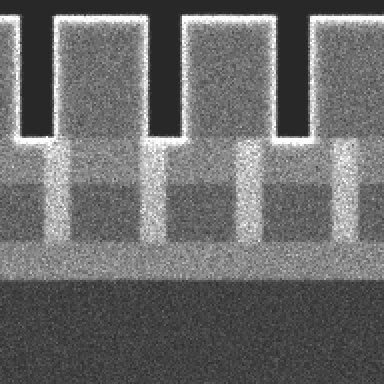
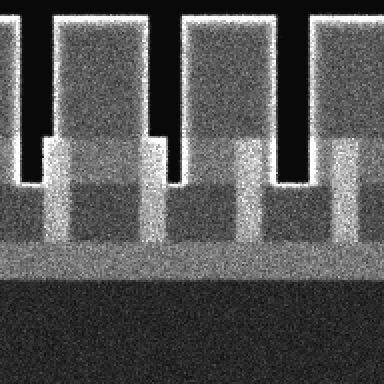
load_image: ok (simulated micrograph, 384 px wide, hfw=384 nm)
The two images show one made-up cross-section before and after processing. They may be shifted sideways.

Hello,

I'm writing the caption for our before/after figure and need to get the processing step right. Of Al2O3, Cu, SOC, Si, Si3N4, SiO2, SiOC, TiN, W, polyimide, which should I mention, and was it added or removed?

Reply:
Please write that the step removed SiO2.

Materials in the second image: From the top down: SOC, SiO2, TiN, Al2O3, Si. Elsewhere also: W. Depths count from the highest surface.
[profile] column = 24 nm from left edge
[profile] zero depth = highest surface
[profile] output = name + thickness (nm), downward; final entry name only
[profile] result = empty 168, TiN 58, Al2O3 38, Si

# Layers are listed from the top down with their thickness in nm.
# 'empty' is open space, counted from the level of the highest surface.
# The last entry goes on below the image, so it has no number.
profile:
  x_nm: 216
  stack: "SOC 122, SiO2 46, TiN 58, Al2O3 38, Si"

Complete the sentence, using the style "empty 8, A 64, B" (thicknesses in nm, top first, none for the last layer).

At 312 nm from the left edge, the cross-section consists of SOC 122, SiO2 46, TiN 58, Al2O3 38, Si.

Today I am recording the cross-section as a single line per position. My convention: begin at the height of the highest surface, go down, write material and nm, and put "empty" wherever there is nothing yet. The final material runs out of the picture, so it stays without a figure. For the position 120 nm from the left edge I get SOC 122, SiO2 46, TiN 58, Al2O3 38, Si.